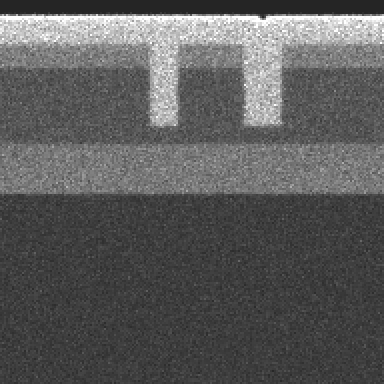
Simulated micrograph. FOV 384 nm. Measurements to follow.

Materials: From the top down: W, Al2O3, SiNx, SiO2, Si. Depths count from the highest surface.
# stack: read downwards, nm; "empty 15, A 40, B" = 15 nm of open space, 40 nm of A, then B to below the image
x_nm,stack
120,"W 28, Al2O3 24, SiNx 76, SiO2 50, Si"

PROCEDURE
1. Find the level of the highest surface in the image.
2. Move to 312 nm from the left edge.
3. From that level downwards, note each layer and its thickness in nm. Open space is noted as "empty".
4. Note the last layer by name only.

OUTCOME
W 28, Al2O3 24, SiNx 76, SiO2 50, Si